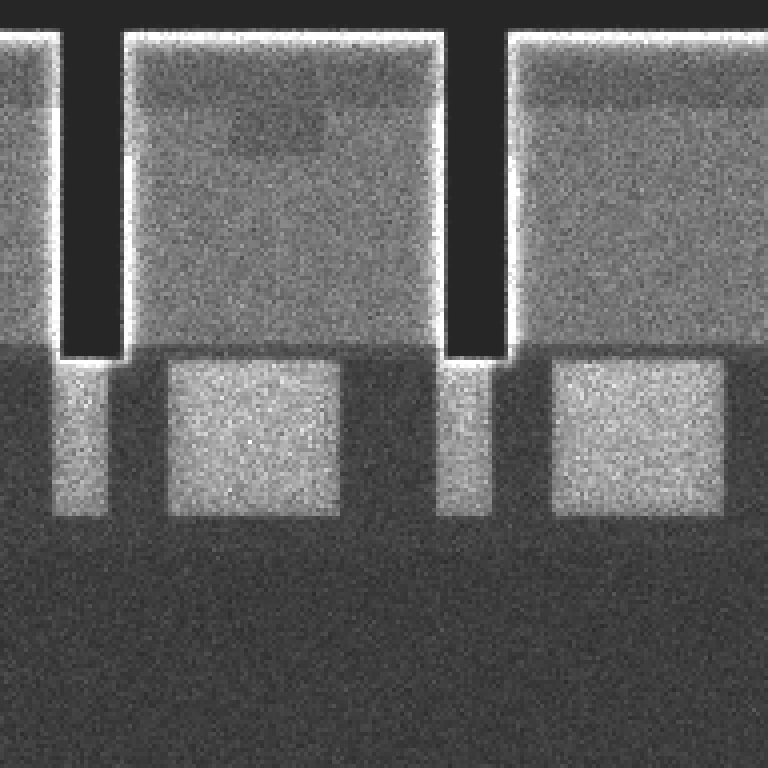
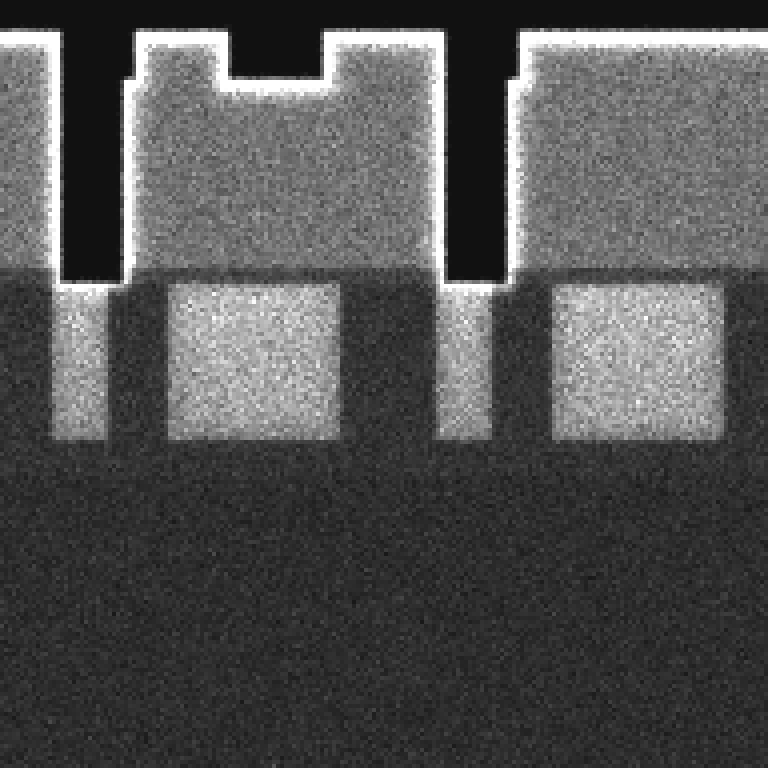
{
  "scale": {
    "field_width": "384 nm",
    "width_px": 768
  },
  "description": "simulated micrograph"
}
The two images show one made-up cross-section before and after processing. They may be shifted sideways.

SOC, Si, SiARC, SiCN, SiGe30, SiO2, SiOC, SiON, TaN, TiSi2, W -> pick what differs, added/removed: SOC removed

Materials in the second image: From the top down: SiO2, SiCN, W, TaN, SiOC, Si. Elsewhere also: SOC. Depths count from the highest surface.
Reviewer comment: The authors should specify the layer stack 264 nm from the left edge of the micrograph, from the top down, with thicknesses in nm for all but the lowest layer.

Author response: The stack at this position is SiO2 118, SiCN 8, SiOC 96, Si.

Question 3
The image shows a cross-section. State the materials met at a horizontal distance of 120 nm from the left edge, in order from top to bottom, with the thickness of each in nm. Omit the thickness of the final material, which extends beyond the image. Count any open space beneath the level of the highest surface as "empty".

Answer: empty 24, SiO2 94, SiCN 8, W 70, TaN 8, SiOC 18, Si